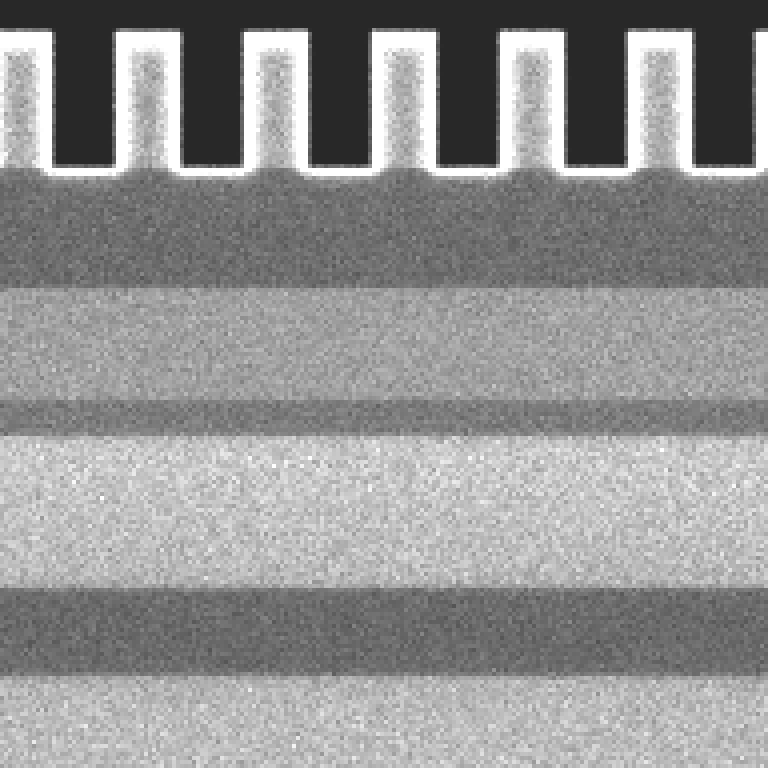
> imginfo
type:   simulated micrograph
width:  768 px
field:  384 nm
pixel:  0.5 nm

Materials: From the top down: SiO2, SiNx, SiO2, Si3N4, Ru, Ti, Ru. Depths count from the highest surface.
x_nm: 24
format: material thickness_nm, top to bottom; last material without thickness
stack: SiO2 68, SiNx 60, SiO2 56, Si3N4 18, Ru 76, Ti 44, Ru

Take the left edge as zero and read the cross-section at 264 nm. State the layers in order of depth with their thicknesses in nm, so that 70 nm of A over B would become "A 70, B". SiO2 68, SiNx 60, SiO2 56, Si3N4 18, Ru 76, Ti 44, Ru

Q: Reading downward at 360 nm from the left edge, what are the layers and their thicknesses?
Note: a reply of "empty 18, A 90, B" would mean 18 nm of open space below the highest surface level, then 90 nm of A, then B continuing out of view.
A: empty 68, SiNx 60, SiO2 56, Si3N4 18, Ru 76, Ti 44, Ru